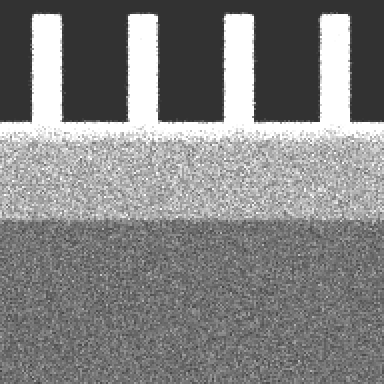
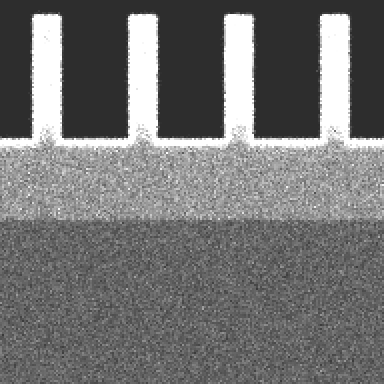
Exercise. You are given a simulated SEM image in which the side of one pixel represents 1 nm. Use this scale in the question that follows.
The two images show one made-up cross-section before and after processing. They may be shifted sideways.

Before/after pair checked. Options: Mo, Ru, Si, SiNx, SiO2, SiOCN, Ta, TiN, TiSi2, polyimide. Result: removed TiN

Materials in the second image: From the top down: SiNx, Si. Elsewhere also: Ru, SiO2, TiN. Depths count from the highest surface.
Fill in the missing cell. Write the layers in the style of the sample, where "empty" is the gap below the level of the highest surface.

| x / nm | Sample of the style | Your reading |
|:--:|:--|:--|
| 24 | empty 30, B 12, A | empty 124, SiNx 80, Si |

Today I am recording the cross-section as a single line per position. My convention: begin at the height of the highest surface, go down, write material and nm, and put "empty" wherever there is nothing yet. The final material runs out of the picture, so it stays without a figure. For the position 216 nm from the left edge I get empty 124, SiNx 80, Si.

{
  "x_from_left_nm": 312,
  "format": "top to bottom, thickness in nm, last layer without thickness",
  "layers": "empty 124, SiNx 80, Si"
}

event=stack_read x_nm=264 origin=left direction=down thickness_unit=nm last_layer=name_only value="empty 124, SiNx 80, Si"